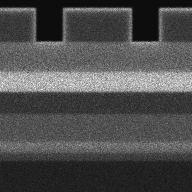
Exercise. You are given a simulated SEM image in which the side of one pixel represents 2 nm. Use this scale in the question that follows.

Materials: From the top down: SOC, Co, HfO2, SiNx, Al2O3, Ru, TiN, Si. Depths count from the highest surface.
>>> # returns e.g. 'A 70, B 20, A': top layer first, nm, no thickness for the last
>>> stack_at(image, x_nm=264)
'empty 68, Co 60, HfO2 40, SiNx 44, Al2O3 56, Ru 22, TiN 16, Si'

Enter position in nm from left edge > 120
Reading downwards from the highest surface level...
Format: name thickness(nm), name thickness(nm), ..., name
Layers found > empty 68, Co 60, HfO2 40, SiNx 44, Al2O3 56, Ru 22, TiN 16, Si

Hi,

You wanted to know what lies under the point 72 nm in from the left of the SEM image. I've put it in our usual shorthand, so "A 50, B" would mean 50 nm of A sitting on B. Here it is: empty 68, Co 60, HfO2 40, SiNx 44, Al2O3 56, Ru 22, TiN 16, Si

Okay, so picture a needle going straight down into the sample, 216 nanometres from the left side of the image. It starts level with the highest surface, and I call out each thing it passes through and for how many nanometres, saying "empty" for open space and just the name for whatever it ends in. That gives SOC 68, Co 60, HfO2 40, SiNx 44, Al2O3 56, Ru 22, TiN 16, Si